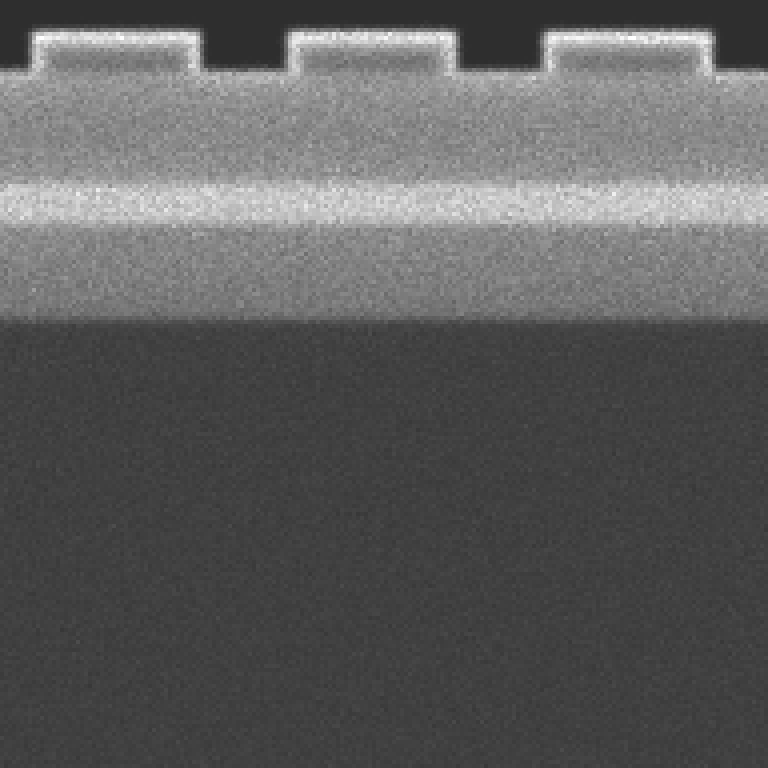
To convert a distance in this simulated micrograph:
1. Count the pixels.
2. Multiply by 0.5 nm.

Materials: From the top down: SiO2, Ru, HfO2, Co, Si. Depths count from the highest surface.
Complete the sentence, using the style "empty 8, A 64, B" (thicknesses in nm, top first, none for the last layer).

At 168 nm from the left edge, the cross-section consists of SiO2 20, Ru 56, HfO2 20, Co 48, Si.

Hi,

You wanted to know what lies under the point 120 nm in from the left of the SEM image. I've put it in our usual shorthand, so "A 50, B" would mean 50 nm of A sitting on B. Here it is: empty 20, Ru 56, HfO2 20, Co 48, Si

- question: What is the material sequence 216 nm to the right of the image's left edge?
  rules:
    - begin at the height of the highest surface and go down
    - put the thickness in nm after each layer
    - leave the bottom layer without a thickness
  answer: SiO2 20, Ru 56, HfO2 20, Co 48, Si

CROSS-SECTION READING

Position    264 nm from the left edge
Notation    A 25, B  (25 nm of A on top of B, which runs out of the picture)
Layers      empty 20, Ru 56, HfO2 20, Co 48, Si